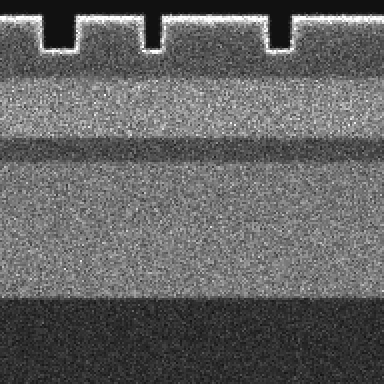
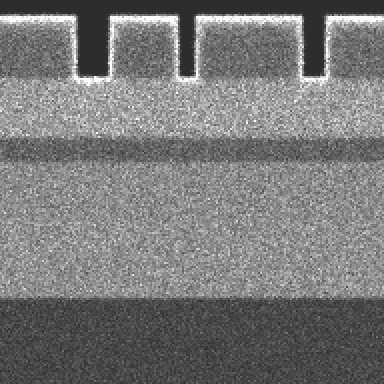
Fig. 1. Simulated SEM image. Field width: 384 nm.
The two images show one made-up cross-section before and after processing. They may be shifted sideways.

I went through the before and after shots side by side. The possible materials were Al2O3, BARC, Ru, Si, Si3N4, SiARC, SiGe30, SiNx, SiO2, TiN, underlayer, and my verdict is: removed, TiN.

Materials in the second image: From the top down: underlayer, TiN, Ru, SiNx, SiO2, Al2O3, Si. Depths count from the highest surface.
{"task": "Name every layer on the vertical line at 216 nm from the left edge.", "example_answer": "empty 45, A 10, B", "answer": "underlayer 22, TiN 40, Ru 60, SiNx 24, SiO2 58, Al2O3 78, Si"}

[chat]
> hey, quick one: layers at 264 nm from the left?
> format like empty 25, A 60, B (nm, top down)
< underlayer 22, TiN 40, Ru 60, SiNx 24, SiO2 58, Al2O3 78, Si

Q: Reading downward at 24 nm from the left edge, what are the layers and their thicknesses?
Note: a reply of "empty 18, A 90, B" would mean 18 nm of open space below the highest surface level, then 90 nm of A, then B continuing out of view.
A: underlayer 22, TiN 40, Ru 60, SiNx 24, SiO2 58, Al2O3 78, Si